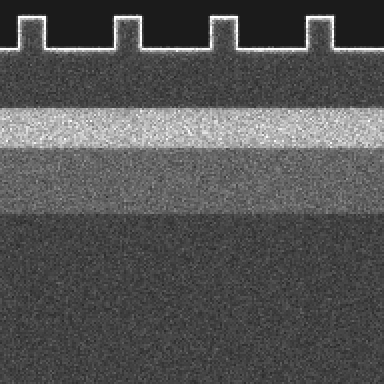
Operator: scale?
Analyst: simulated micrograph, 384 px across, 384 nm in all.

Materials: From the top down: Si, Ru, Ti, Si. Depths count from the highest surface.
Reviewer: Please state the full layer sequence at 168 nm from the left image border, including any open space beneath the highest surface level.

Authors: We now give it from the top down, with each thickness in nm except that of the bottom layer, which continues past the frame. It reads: empty 32, Si 60, Ru 40, Ti 66, Si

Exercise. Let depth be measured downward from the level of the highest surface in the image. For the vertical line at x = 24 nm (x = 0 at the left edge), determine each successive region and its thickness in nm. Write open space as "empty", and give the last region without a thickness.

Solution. Si 92, Ru 40, Ti 66, Si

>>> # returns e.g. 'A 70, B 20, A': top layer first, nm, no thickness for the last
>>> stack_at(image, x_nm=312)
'Si 92, Ru 40, Ti 66, Si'